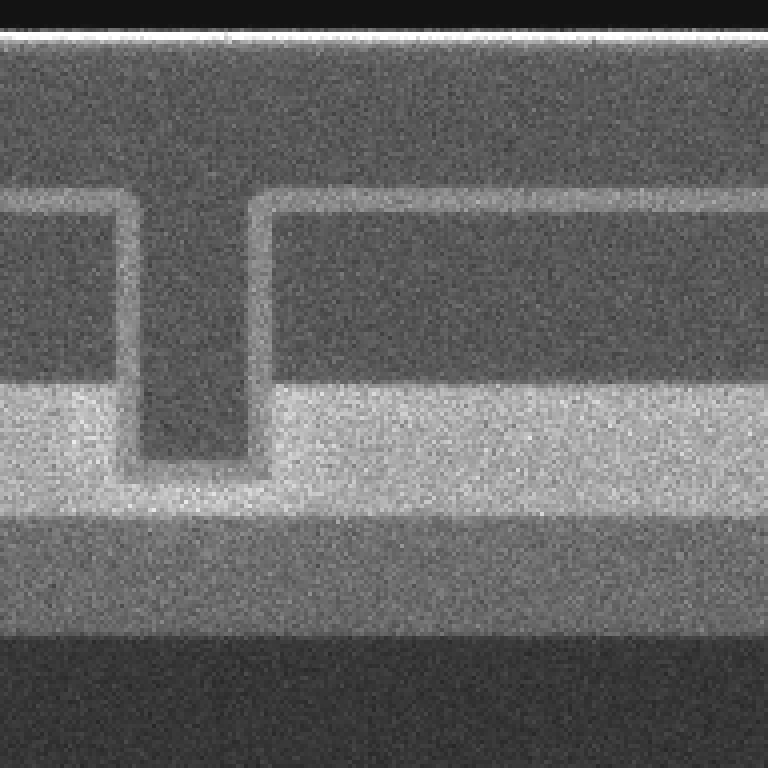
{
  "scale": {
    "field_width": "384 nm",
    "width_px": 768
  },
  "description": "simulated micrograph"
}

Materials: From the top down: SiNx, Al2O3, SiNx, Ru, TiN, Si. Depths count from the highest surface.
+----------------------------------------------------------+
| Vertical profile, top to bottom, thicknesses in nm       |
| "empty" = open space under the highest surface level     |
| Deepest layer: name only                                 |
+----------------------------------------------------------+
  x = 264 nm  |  SiNx 78, Al2O3 12, SiNx 86, Ru 66, TiN 60, Si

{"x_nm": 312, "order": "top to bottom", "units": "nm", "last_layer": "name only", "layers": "SiNx 78, Al2O3 12, SiNx 86, Ru 66, TiN 60, Si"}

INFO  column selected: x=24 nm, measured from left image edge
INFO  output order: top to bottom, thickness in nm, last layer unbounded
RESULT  SiNx 78, Al2O3 12, SiNx 86, Ru 66, TiN 60, Si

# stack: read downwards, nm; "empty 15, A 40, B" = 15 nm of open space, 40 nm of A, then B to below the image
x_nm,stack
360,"SiNx 78, Al2O3 12, SiNx 86, Ru 66, TiN 60, Si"